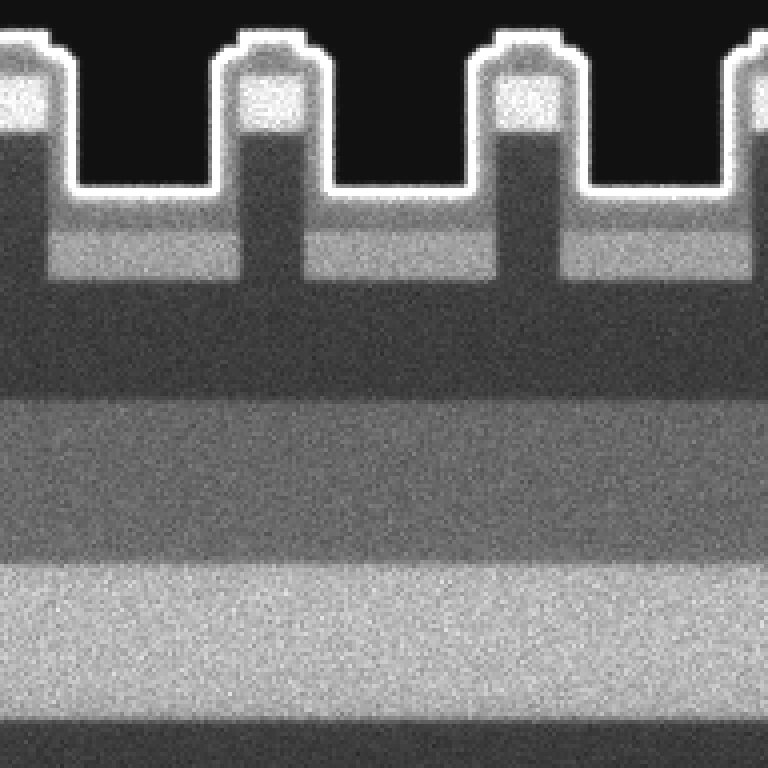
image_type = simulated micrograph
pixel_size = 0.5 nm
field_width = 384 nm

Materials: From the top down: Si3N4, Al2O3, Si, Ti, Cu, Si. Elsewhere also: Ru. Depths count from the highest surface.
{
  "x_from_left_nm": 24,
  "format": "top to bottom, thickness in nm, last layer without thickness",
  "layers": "empty 8, Si3N4 92, Al2O3 24, Si 60, Ti 82, Cu 78, Si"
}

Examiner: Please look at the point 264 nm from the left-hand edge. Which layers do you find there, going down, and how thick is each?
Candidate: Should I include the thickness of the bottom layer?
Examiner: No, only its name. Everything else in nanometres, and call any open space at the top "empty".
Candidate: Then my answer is Si3N4 22, Ru 28, Si 134, Ti 82, Cu 78, Si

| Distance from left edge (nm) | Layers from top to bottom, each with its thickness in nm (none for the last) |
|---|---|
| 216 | empty 78, Si3N4 22, Al2O3 24, Si 60, Ti 82, Cu 78, Si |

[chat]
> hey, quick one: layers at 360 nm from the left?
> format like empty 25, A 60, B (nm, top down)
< empty 78, Si3N4 22, Al2O3 24, Si 60, Ti 82, Cu 78, Si